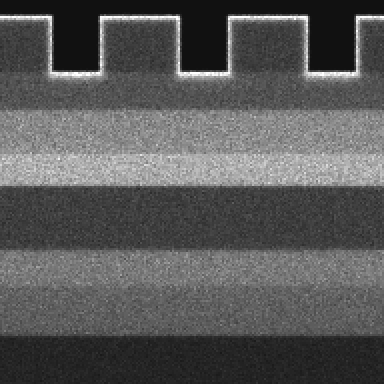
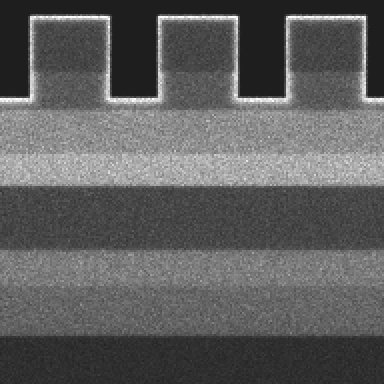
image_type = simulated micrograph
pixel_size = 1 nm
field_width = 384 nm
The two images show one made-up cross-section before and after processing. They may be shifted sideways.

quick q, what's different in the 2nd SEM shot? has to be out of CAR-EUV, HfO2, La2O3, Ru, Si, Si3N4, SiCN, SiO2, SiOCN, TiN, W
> SiO2 removed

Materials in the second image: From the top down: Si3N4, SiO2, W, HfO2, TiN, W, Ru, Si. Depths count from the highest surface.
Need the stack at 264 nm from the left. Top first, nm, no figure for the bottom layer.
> empty 82, SiO2 12, W 44, HfO2 32, TiN 64, W 36, Ru 50, Si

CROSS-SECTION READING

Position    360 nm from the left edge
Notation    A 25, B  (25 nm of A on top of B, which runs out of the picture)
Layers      Si3N4 56, SiO2 38, W 44, HfO2 32, TiN 64, W 36, Ru 50, Si